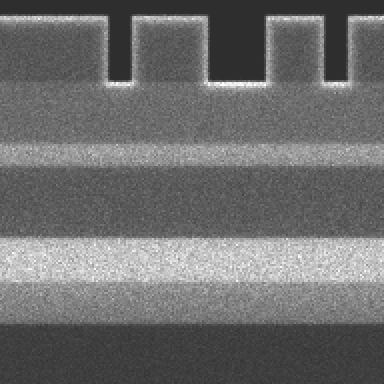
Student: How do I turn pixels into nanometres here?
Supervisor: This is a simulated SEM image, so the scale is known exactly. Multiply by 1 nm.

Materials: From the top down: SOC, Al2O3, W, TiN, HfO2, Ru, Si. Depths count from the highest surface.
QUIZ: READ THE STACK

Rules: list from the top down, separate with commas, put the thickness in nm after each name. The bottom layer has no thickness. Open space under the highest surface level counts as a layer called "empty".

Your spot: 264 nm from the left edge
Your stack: empty 66, Al2O3 62, W 22, TiN 72, HfO2 44, Ru 42, Si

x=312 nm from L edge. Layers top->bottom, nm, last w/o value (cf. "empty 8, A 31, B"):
SOC 66, Al2O3 62, W 22, TiN 72, HfO2 44, Ru 42, Si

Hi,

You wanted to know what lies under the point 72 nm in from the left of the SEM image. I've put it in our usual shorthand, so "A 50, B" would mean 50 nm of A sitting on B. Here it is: SOC 66, Al2O3 62, W 22, TiN 72, HfO2 44, Ru 42, Si